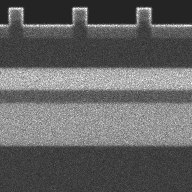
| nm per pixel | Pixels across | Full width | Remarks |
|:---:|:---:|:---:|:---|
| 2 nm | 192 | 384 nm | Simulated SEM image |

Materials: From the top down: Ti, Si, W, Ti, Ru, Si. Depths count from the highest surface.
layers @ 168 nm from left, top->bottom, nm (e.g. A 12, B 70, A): Ti 26, Si 94, W 44, Ti 26, Ru 86, Si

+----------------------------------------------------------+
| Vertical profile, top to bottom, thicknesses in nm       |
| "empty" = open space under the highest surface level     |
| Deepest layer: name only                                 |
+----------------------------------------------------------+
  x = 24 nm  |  Ti 26, Si 94, W 44, Ti 26, Ru 86, Si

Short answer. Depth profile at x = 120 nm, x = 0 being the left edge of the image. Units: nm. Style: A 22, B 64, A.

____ empty 34, Ti 26, Si 60, W 44, Ti 26, Ru 86, Si